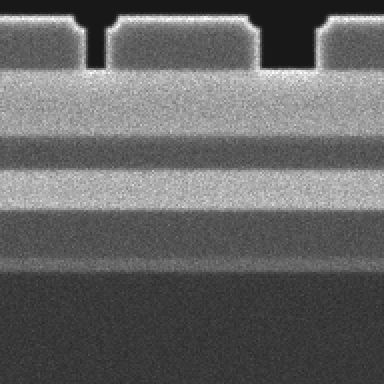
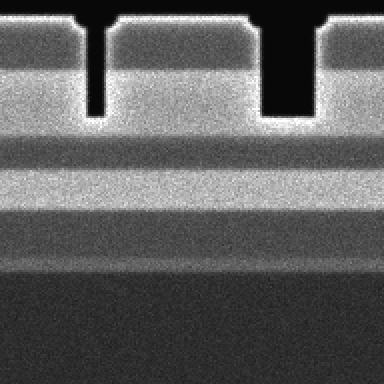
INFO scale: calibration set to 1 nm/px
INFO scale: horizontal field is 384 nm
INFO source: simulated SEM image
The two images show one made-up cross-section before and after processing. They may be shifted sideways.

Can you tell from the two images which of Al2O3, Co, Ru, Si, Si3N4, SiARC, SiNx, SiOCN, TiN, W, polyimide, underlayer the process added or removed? Yes, it removed Ru.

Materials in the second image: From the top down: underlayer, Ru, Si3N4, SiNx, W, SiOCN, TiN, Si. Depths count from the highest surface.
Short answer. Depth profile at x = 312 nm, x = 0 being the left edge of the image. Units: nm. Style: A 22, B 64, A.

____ empty 102, Ru 18, Si3N4 8, SiNx 26, W 40, SiOCN 48, TiN 14, Si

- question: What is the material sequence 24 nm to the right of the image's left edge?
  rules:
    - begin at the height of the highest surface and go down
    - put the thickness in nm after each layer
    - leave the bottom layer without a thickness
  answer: underlayer 54, Ru 66, Si3N4 8, SiNx 26, W 40, SiOCN 48, TiN 14, Si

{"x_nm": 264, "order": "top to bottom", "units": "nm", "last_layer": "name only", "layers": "empty 102, Ru 18, Si3N4 8, SiNx 26, W 40, SiOCN 48, TiN 14, Si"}